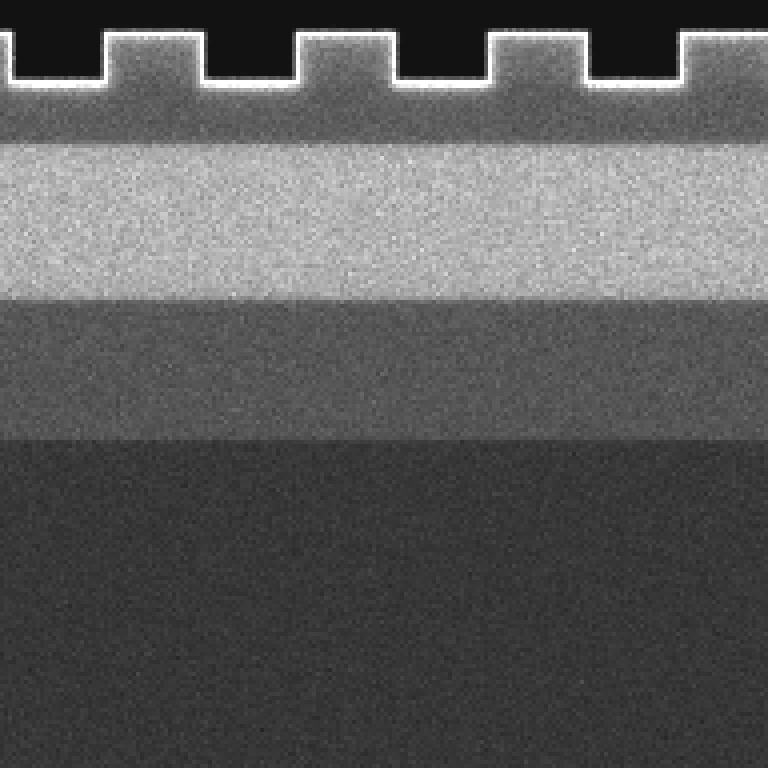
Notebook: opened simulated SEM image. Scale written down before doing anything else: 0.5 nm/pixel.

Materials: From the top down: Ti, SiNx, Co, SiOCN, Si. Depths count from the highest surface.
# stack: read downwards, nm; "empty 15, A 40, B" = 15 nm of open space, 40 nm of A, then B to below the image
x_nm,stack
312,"empty 24, SiNx 32, Co 78, SiOCN 70, Si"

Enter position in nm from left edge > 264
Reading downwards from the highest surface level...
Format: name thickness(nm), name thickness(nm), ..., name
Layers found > Ti 24, SiNx 32, Co 78, SiOCN 70, Si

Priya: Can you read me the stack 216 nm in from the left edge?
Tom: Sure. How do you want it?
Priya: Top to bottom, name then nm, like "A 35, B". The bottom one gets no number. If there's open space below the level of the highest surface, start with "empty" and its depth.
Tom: empty 24, SiNx 32, Co 78, SiOCN 70, Si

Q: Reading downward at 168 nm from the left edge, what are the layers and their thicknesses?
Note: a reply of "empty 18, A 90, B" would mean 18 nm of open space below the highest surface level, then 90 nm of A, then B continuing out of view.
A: Ti 24, SiNx 32, Co 78, SiOCN 70, Si